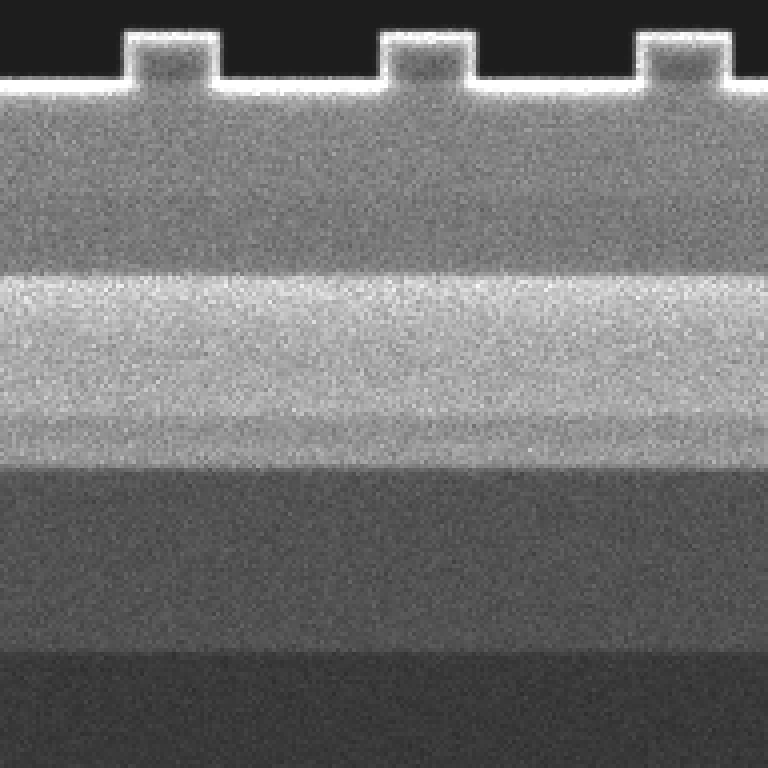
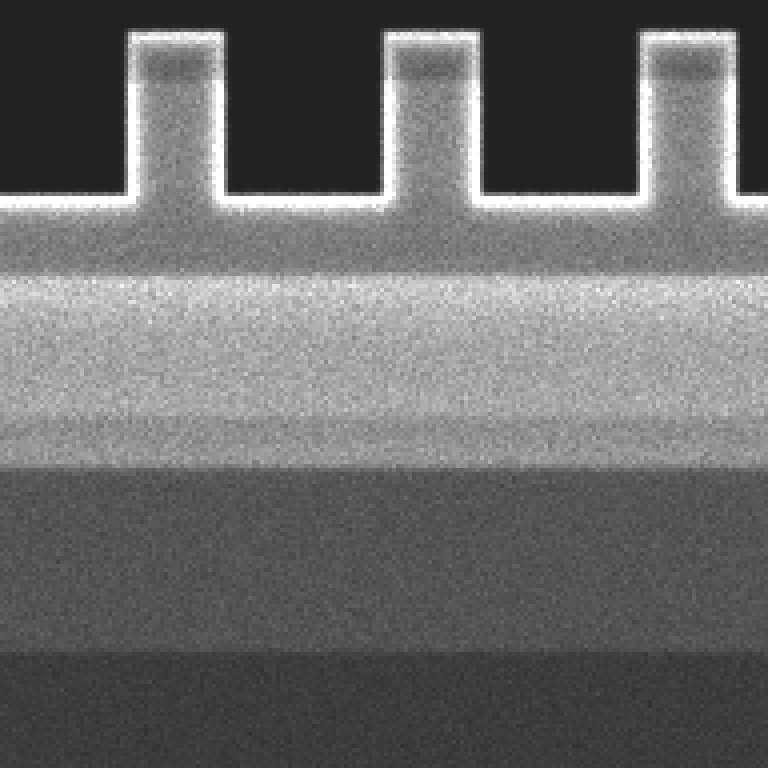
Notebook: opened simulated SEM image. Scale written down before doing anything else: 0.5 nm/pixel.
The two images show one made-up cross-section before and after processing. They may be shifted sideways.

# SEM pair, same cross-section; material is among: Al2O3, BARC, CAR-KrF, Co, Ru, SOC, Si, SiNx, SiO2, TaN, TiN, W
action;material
removed;Al2O3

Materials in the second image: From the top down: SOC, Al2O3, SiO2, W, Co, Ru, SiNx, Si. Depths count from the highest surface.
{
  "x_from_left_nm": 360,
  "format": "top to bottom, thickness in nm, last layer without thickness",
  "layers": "SOC 24, Al2O3 58, SiO2 40, W 70, Co 14, Ru 12, SiNx 92, Si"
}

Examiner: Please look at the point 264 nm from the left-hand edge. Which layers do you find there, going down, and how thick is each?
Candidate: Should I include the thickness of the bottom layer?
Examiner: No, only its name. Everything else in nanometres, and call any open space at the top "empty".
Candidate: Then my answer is empty 82, SiO2 40, W 70, Co 14, Ru 12, SiNx 92, Si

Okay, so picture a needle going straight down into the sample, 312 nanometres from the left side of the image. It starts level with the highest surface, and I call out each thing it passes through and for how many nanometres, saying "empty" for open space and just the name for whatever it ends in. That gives empty 82, SiO2 40, W 70, Co 14, Ru 12, SiNx 92, Si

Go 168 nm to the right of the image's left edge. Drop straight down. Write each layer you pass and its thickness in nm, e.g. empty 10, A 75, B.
empty 82, SiO2 40, W 70, Co 14, Ru 12, SiNx 92, Si